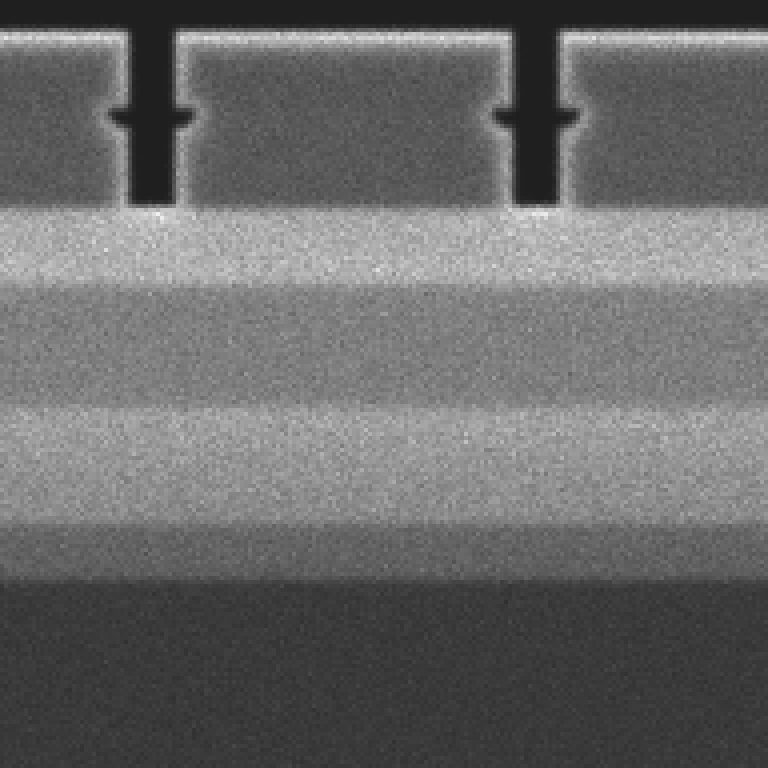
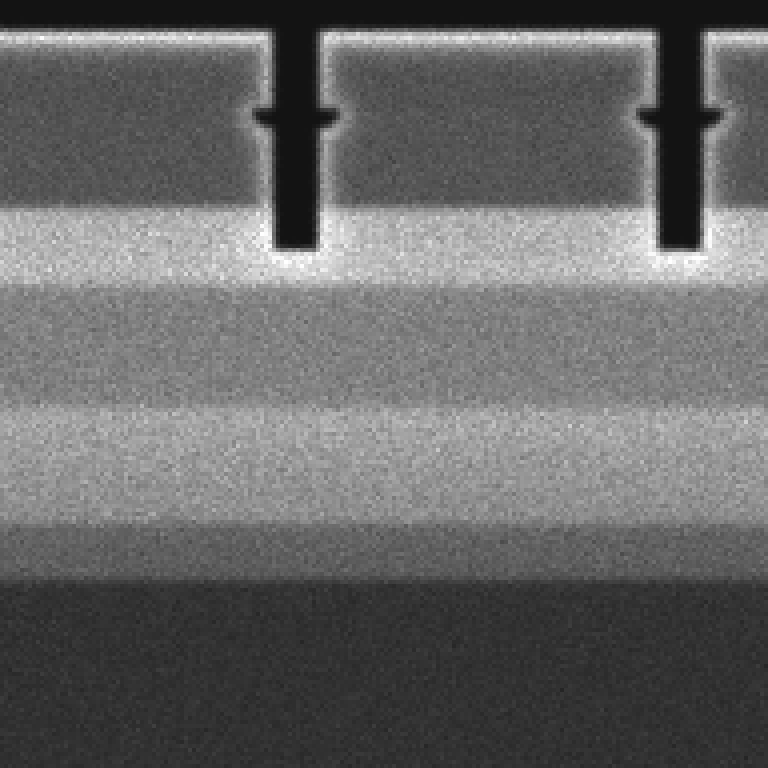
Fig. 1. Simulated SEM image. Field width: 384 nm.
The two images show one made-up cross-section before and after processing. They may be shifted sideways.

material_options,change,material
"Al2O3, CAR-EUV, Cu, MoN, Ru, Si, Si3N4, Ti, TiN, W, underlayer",removed,Ru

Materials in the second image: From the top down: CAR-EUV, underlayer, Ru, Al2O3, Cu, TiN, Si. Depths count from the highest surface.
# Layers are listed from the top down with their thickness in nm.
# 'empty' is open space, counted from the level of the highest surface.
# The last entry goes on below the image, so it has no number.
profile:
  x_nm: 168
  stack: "CAR-EUV 38, empty 6, underlayer 44, Ru 38, Al2O3 62, Cu 58, TiN 28, Si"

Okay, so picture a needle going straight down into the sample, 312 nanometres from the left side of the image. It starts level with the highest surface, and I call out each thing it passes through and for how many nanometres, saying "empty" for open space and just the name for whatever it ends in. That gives CAR-EUV 38, underlayer 50, Ru 38, Al2O3 62, Cu 58, TiN 28, Si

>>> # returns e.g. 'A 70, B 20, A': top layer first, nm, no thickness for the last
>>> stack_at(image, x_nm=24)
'CAR-EUV 38, underlayer 50, Ru 38, Al2O3 62, Cu 58, TiN 28, Si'